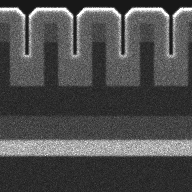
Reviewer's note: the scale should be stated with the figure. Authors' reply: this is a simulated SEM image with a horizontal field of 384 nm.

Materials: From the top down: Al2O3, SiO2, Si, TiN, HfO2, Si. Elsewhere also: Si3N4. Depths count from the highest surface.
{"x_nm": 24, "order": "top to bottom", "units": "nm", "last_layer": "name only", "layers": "Al2O3 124, SiO2 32, Si 60, TiN 48, HfO2 32, Si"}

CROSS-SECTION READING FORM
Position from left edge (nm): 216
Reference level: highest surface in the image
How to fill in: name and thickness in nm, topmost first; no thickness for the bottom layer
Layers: Al2O3 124, SiO2 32, Si 60, TiN 48, HfO2 32, Si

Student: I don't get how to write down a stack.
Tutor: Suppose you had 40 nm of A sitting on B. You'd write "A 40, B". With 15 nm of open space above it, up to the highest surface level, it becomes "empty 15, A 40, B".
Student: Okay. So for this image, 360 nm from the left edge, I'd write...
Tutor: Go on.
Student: Al2O3 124, SiO2 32, Si 60, TiN 48, HfO2 32, Si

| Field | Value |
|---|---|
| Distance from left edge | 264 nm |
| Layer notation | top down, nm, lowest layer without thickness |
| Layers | Al2O3 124, SiO2 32, Si 60, TiN 48, HfO2 32, Si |